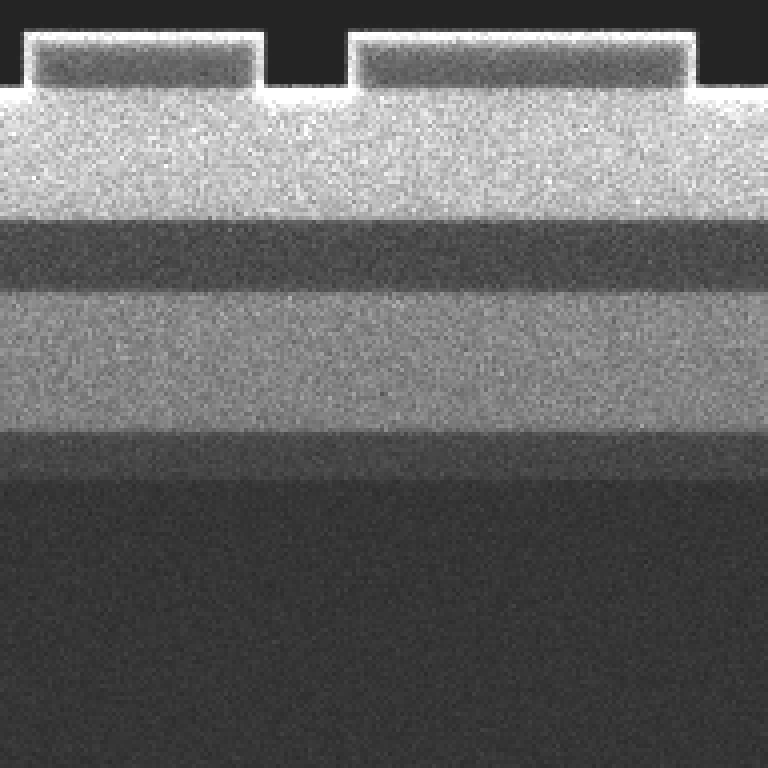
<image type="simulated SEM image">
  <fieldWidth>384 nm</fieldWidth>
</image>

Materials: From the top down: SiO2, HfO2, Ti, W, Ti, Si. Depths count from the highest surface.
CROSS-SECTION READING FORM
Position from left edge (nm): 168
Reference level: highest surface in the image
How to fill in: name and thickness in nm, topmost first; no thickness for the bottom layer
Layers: empty 28, HfO2 66, Ti 36, W 70, Ti 24, Si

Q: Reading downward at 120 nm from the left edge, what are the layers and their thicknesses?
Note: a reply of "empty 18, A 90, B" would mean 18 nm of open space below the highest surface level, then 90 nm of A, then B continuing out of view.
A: SiO2 28, HfO2 66, Ti 36, W 70, Ti 24, Si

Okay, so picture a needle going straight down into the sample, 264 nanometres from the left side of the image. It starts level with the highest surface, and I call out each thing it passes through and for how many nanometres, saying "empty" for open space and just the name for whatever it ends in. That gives SiO2 28, HfO2 66, Ti 36, W 70, Ti 24, Si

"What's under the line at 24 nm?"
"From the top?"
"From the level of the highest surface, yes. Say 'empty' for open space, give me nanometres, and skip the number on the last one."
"SiO2 28, HfO2 66, Ti 36, W 70, Ti 24, Si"